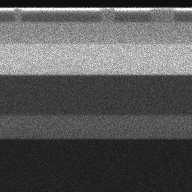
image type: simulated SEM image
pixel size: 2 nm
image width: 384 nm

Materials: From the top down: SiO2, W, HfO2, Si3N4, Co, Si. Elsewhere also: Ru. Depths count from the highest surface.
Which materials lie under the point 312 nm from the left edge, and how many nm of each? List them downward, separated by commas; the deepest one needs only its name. Ru 28, W 44, HfO2 62, Si3N4 80, Co 48, Si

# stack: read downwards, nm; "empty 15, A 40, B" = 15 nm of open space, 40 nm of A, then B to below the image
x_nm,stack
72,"SiO2 28, W 44, HfO2 62, Si3N4 80, Co 48, Si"